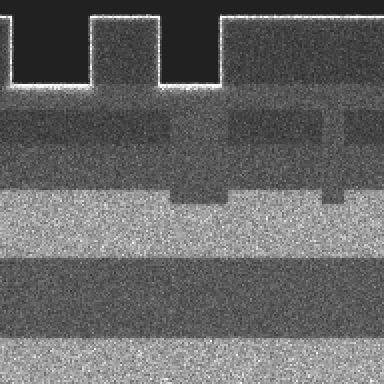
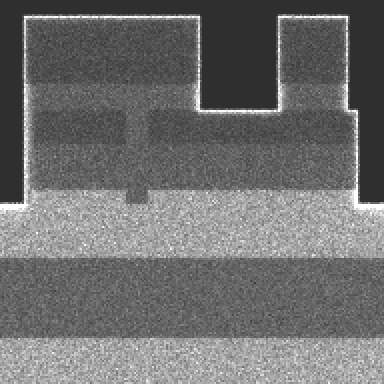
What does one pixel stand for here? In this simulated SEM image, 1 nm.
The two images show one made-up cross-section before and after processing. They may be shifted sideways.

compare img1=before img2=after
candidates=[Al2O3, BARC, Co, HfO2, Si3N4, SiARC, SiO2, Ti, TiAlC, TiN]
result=removed:SiO2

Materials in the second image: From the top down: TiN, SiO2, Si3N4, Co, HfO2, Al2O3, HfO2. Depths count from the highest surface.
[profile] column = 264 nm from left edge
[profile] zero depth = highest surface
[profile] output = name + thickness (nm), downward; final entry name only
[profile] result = empty 94, Si3N4 34, Co 46, HfO2 68, Al2O3 80, HfO2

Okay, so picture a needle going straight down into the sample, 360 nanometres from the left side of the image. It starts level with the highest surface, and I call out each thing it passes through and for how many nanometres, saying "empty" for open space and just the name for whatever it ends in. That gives empty 188, HfO2 54, Al2O3 80, HfO2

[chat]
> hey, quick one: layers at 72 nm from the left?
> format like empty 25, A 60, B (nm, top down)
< TiN 68, SiO2 26, Si3N4 34, Co 46, HfO2 68, Al2O3 80, HfO2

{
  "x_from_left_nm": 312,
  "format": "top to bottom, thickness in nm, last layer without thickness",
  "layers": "TiN 68, SiO2 26, Si3N4 34, Co 46, HfO2 68, Al2O3 80, HfO2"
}